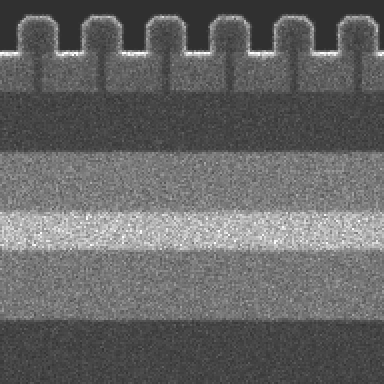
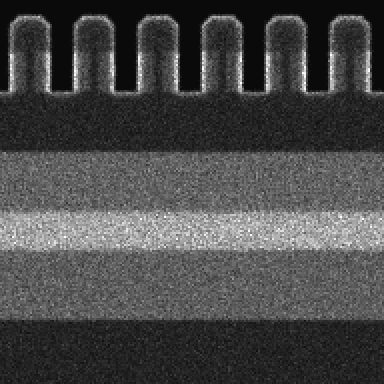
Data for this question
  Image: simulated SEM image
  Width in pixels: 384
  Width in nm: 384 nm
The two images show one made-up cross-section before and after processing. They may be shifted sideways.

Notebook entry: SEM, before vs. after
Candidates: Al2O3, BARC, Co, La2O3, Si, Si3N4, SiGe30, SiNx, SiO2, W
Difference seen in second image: Si3N4 removed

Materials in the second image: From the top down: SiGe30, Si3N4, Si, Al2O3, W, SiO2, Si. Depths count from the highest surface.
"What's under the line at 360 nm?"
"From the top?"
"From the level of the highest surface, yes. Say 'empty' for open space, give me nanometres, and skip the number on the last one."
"SiGe30 36, Si3N4 40, Si 60, Al2O3 60, W 38, SiO2 70, Si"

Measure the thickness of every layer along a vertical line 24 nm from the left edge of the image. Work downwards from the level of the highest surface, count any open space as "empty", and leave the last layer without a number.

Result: SiGe30 36, Si3N4 40, Si 60, Al2O3 60, W 38, SiO2 70, Si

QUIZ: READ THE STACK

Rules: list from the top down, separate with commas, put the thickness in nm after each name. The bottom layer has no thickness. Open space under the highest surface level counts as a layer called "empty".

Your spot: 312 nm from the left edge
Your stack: empty 76, Si 60, Al2O3 60, W 38, SiO2 70, Si